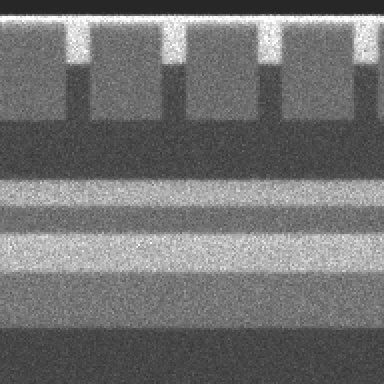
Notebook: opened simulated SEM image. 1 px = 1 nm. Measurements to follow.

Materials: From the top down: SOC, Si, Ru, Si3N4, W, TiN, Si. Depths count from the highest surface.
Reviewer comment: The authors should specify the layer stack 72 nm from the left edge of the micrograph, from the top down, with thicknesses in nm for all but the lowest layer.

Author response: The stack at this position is Ru 48, Si 116, Ru 26, Si3N4 28, W 38, TiN 56, Si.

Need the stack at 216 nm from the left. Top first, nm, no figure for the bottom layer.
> SOC 104, Si 60, Ru 26, Si3N4 28, W 38, TiN 56, Si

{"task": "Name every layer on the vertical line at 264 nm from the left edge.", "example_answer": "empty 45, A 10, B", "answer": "Ru 48, Si 116, Ru 26, Si3N4 28, W 38, TiN 56, Si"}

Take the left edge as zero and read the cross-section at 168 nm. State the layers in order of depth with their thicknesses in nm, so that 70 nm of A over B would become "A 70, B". Ru 48, Si 116, Ru 26, Si3N4 28, W 38, TiN 56, Si